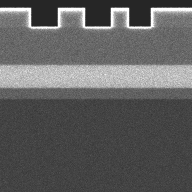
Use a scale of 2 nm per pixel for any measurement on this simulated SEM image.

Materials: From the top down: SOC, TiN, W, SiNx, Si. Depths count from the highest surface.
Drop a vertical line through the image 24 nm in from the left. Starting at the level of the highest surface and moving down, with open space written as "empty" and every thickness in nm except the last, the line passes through SOC 38, TiN 76, W 46, SiNx 22, Si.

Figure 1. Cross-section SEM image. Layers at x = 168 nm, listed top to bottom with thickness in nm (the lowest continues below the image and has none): SOC 38, TiN 76, W 46, SiNx 22, Si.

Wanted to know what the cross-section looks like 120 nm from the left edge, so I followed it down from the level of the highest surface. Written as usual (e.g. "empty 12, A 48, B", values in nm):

SOC 38, TiN 76, W 46, SiNx 22, Si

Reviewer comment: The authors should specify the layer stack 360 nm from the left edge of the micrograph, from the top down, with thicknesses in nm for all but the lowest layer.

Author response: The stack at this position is SOC 38, TiN 76, W 46, SiNx 22, Si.